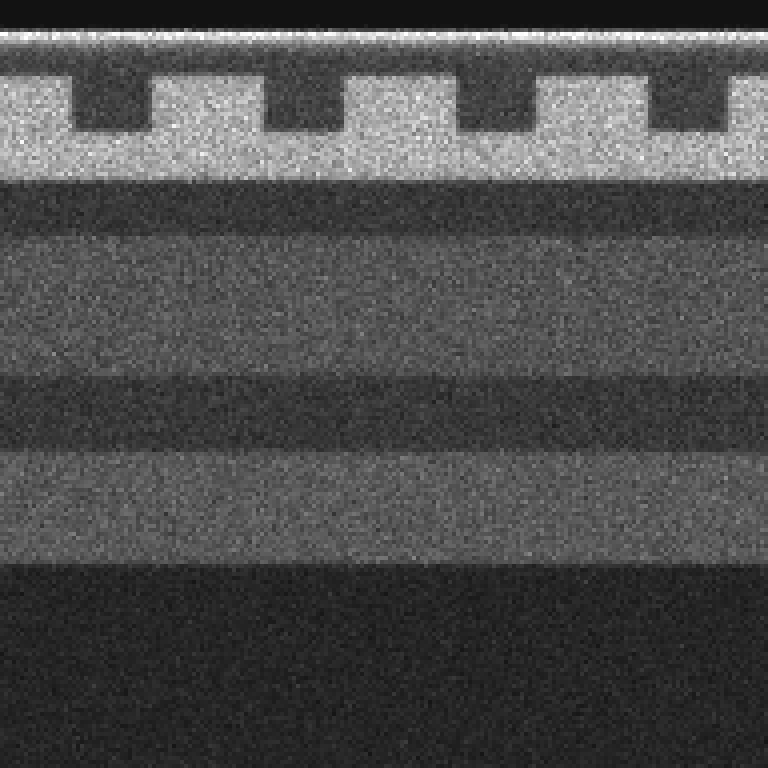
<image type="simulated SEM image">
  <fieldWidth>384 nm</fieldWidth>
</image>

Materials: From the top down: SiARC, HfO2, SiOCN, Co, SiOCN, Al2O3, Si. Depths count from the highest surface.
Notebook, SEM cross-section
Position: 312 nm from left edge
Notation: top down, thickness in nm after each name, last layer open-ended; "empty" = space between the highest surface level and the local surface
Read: SiARC 22, HfO2 52, SiOCN 28, Co 70, SiOCN 38, Al2O3 56, Si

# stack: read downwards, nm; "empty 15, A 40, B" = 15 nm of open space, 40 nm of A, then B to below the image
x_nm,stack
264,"SiARC 50, HfO2 24, SiOCN 28, Co 70, SiOCN 38, Al2O3 56, Si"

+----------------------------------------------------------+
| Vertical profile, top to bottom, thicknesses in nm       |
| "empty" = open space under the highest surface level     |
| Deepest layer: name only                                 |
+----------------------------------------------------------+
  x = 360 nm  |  SiARC 50, HfO2 24, SiOCN 28, Co 70, SiOCN 38, Al2O3 56, Si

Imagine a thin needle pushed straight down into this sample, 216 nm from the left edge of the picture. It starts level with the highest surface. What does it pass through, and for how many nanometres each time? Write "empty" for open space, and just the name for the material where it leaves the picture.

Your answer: SiARC 22, HfO2 52, SiOCN 28, Co 70, SiOCN 38, Al2O3 56, Si